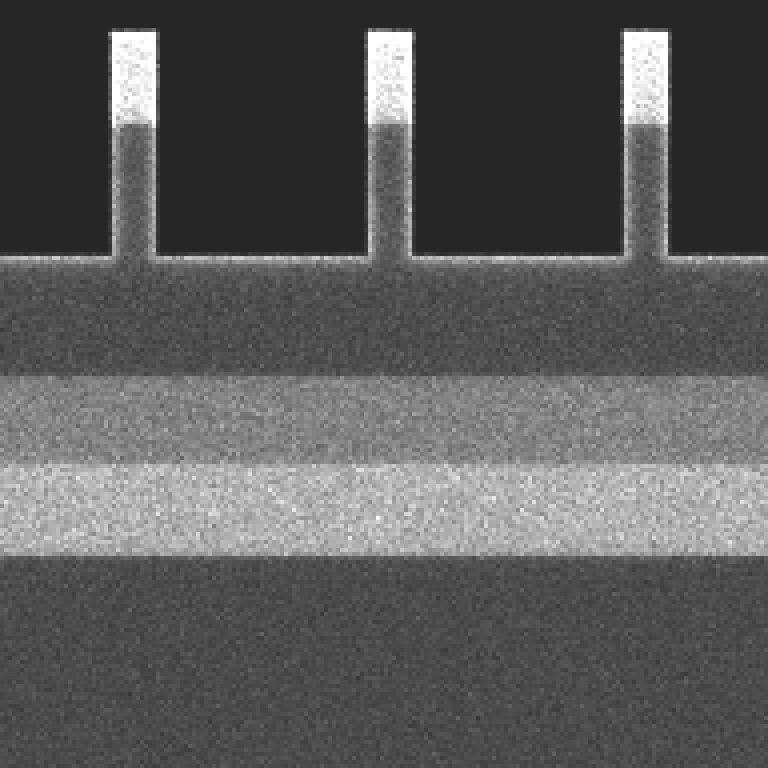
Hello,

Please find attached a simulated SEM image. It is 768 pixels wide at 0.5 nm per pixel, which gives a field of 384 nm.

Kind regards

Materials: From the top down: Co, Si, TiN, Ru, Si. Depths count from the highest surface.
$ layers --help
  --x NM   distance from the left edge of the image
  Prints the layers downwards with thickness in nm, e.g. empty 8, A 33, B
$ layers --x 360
empty 112, Si 60, TiN 44, Ru 46, Si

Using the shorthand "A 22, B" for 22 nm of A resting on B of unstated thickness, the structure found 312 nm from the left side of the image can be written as Co 46, Si 126, TiN 44, Ru 46, Si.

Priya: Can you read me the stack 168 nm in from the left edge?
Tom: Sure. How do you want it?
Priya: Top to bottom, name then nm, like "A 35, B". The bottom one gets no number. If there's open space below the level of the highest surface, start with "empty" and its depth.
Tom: empty 112, Si 60, TiN 44, Ru 46, Si